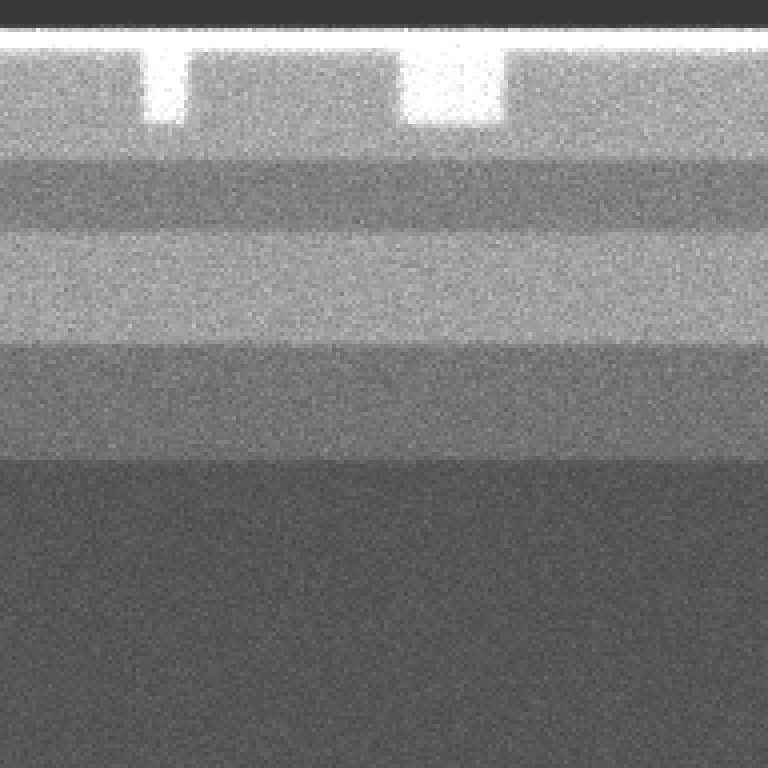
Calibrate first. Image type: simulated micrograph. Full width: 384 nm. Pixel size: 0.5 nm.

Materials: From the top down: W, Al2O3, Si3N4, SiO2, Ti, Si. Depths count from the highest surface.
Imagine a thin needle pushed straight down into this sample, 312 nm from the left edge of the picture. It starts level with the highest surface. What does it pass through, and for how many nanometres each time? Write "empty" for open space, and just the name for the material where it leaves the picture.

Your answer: Al2O3 64, Si3N4 36, SiO2 56, Ti 58, Si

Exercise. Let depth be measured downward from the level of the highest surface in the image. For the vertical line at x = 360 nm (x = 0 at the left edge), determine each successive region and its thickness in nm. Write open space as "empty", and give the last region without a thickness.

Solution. Al2O3 64, Si3N4 36, SiO2 56, Ti 58, Si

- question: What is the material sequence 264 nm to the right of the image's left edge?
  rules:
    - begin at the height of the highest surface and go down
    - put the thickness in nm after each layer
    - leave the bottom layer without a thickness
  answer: Al2O3 64, Si3N4 36, SiO2 56, Ti 58, Si